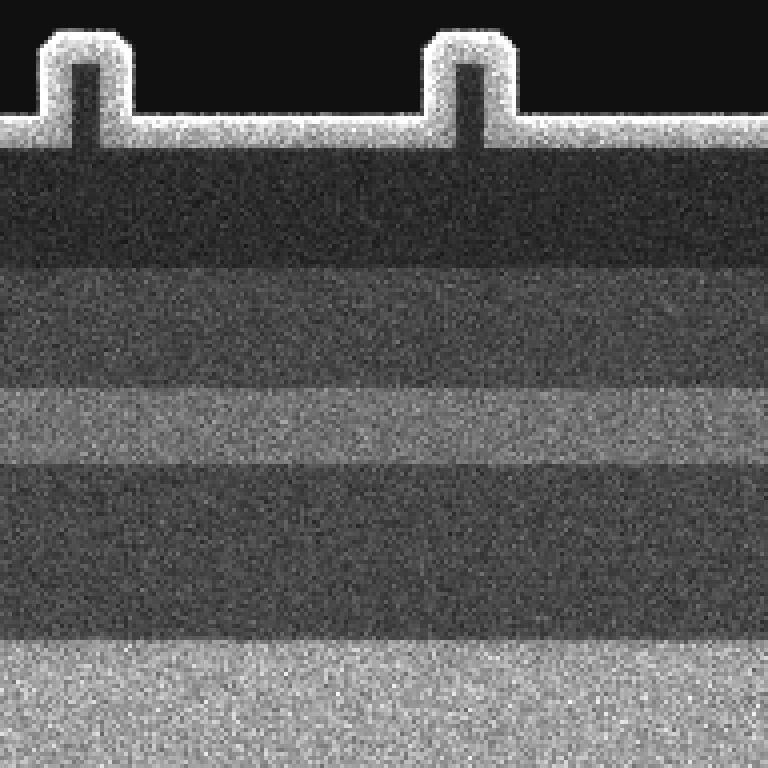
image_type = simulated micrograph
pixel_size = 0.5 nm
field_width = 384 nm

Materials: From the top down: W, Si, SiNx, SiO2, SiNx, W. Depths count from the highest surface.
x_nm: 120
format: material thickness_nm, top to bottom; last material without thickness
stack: empty 42, W 16, Si 60, SiNx 60, SiO2 38, SiNx 88, W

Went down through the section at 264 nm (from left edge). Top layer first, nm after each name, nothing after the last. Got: empty 42, W 16, Si 60, SiNx 60, SiO2 38, SiNx 88, W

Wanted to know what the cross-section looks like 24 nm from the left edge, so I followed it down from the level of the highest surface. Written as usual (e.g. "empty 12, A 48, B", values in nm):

empty 4, W 54, Si 60, SiNx 60, SiO2 38, SiNx 88, W